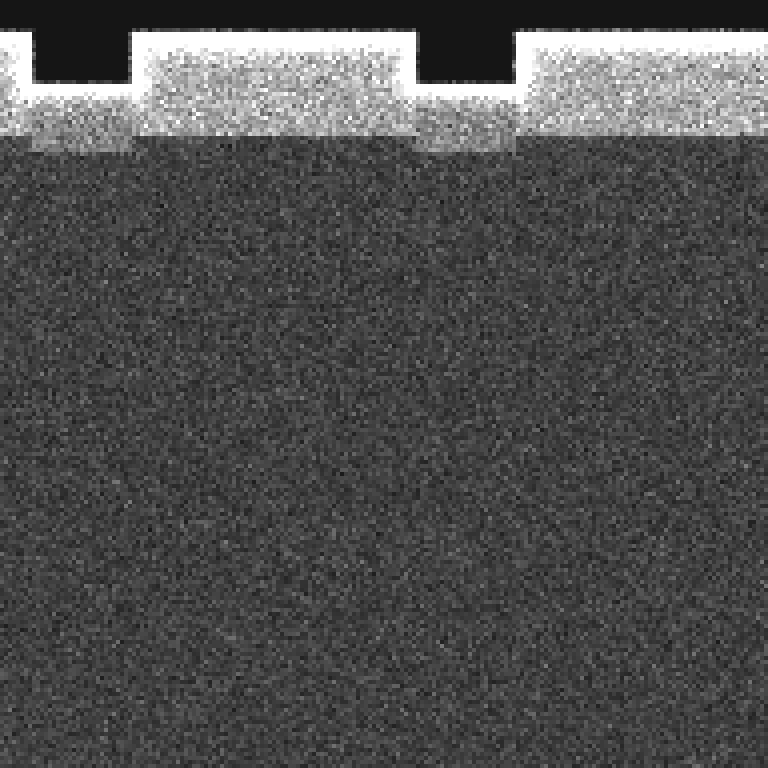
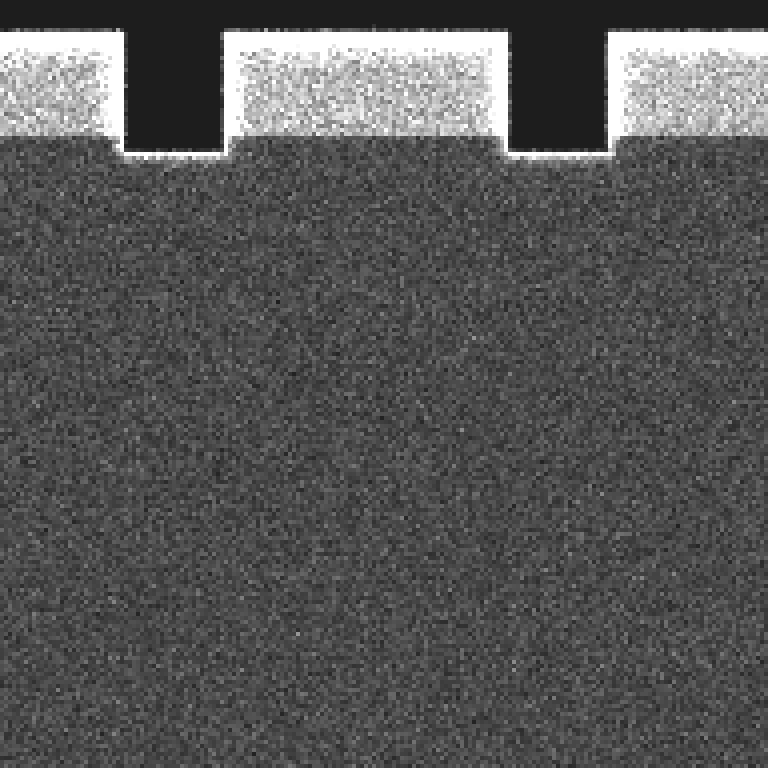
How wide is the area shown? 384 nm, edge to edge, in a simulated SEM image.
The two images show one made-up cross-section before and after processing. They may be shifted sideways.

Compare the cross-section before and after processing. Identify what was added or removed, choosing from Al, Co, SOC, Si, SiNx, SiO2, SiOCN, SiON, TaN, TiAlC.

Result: SOC removed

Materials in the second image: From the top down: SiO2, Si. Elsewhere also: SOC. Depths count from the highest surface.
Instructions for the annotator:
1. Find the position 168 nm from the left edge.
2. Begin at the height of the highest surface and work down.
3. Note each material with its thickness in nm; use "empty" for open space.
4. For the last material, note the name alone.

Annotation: SiO2 52, Si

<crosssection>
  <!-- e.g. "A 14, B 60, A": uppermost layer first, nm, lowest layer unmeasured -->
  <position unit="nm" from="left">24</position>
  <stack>SiO2 52, Si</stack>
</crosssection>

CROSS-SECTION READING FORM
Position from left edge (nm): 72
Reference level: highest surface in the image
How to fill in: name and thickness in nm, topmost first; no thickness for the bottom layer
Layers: empty 60, Si